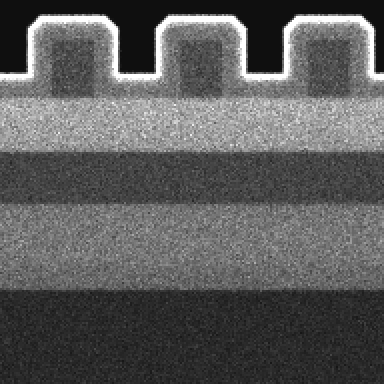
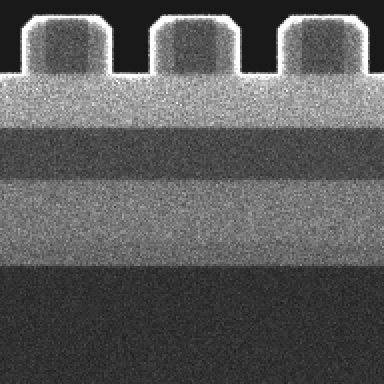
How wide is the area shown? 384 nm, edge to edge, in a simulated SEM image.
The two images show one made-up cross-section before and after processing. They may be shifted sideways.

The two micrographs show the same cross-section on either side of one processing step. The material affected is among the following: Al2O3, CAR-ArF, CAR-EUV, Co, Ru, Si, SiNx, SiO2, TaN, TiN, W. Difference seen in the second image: Al2O3 removed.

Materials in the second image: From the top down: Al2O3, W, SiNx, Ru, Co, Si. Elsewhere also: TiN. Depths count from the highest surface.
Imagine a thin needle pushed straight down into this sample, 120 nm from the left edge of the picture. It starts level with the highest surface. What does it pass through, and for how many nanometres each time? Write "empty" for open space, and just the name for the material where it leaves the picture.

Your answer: empty 58, W 54, SiNx 52, Ru 62, Co 24, Si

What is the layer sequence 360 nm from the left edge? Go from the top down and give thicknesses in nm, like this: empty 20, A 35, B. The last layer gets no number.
empty 6, Al2O3 52, W 54, SiNx 52, Ru 62, Co 24, Si